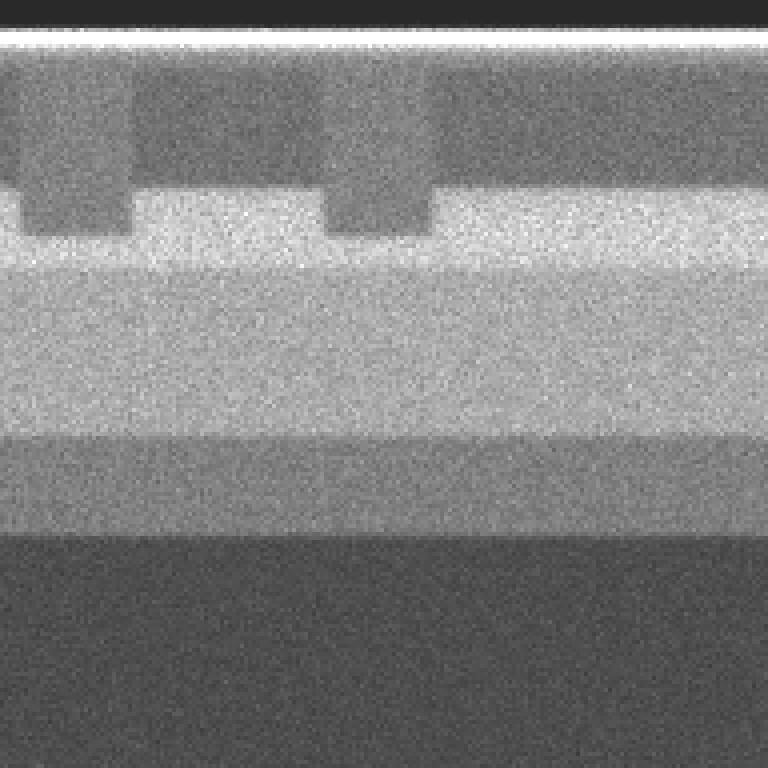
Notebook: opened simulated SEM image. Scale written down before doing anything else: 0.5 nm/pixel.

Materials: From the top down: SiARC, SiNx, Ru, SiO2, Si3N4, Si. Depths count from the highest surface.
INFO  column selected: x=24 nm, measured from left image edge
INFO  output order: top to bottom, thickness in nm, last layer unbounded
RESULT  SiARC 102, Ru 16, SiO2 84, Si3N4 50, Si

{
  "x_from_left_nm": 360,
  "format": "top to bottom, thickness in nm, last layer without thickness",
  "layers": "SiARC 18, SiNx 60, Ru 40, SiO2 84, Si3N4 50, Si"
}